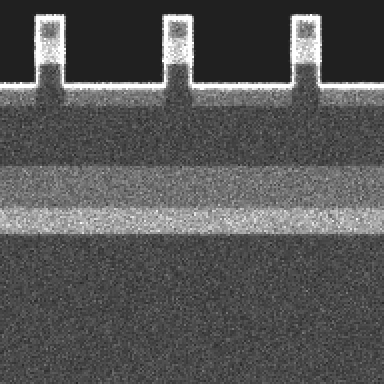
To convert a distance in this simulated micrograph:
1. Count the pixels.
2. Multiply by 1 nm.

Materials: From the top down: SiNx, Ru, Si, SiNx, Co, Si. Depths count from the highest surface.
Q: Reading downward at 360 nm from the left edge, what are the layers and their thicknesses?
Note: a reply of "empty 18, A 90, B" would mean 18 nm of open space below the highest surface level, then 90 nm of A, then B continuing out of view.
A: empty 68, SiNx 22, Si 60, SiNx 42, Co 26, Si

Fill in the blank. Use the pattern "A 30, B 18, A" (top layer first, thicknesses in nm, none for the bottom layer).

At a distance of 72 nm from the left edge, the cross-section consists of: empty 68, SiNx 22, Si 60, SiNx 42, Co 26, Si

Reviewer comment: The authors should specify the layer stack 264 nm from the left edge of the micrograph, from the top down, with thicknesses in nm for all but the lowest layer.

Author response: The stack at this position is empty 68, SiNx 22, Si 60, SiNx 42, Co 26, Si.